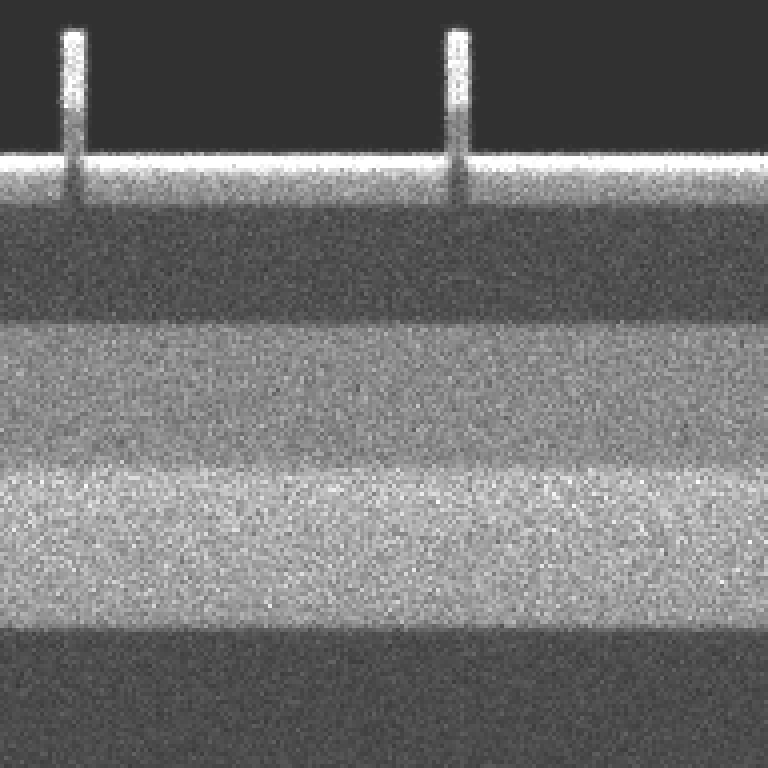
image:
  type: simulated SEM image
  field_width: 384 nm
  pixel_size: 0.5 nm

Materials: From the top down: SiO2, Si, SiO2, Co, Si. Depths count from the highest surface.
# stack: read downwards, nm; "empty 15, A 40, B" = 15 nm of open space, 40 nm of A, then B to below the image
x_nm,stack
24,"empty 62, SiO2 24, Si 60, SiO2 72, Co 80, Si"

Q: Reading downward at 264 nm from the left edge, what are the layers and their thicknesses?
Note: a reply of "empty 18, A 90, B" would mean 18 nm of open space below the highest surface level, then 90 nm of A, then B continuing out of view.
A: empty 62, SiO2 24, Si 60, SiO2 72, Co 80, Si